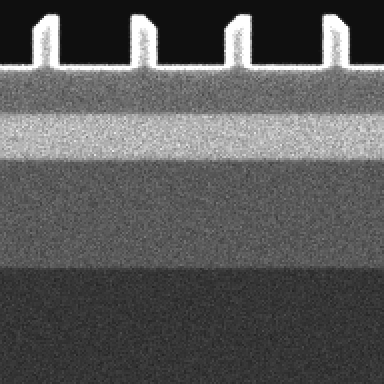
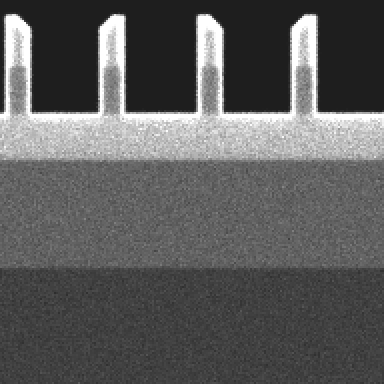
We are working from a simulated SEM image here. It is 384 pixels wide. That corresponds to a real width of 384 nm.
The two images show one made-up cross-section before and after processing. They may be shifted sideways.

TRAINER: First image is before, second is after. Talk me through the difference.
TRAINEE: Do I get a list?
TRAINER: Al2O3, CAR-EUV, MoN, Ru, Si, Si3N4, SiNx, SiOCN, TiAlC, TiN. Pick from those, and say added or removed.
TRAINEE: removed: TiN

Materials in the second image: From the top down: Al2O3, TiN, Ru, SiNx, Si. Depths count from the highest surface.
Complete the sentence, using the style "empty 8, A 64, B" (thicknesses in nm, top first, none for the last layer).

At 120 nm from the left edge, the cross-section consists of Al2O3 50, TiN 48, Ru 46, SiNx 108, Si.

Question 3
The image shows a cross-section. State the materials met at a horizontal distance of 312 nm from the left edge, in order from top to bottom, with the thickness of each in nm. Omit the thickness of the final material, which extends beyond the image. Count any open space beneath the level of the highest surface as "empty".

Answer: Al2O3 50, TiN 48, Ru 46, SiNx 108, Si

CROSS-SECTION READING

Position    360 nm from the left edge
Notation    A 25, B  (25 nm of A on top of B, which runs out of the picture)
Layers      empty 98, Ru 46, SiNx 108, Si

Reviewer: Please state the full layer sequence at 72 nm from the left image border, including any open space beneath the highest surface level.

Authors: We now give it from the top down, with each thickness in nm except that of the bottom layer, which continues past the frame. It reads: empty 98, Ru 46, SiNx 108, Si